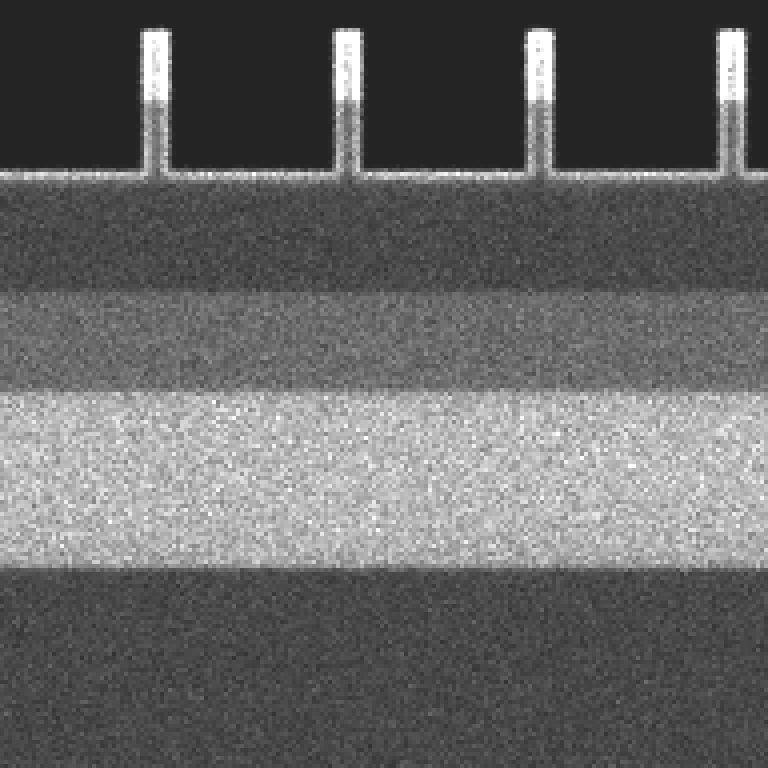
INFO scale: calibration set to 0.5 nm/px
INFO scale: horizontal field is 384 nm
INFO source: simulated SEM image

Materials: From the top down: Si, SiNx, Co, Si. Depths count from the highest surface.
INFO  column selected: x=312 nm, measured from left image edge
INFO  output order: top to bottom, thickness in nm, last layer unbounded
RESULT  empty 70, Si 60, SiNx 50, Co 88, Si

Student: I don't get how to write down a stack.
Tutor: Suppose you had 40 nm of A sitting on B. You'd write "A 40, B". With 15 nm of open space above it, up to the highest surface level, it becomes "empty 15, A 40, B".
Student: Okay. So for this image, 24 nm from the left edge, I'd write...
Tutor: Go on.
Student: empty 70, Si 60, SiNx 50, Co 88, Si